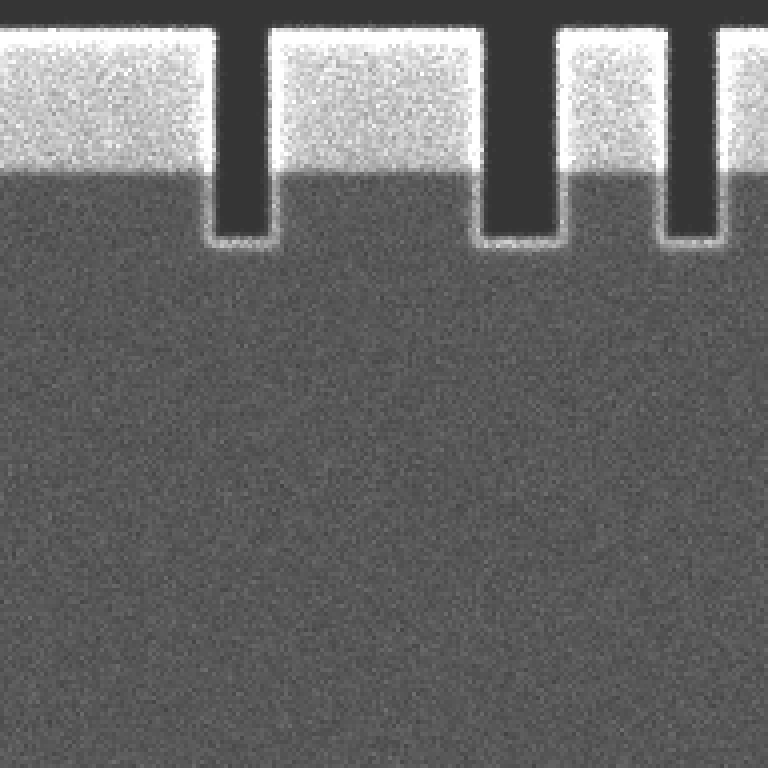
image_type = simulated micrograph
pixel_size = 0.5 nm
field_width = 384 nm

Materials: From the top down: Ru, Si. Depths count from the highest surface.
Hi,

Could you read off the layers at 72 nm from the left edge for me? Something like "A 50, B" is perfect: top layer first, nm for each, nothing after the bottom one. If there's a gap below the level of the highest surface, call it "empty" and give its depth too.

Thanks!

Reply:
Ru 70, Si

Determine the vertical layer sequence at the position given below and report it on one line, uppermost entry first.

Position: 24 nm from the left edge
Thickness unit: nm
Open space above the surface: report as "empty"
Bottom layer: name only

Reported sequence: Ru 70, Si